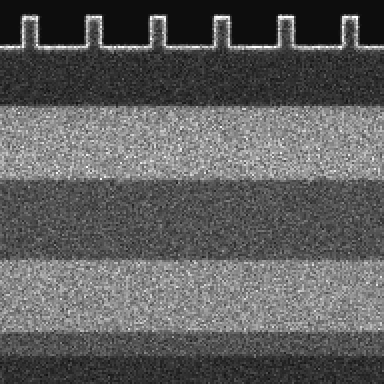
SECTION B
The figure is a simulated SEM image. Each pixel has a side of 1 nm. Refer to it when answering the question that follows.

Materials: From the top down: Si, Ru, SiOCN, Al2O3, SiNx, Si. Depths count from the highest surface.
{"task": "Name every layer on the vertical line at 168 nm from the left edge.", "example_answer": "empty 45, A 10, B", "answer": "empty 30, Si 60, Ru 74, SiOCN 80, Al2O3 72, SiNx 24, Si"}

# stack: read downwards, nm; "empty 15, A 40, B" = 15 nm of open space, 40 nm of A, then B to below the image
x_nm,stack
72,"empty 30, Si 60, Ru 74, SiOCN 80, Al2O3 72, SiNx 24, Si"